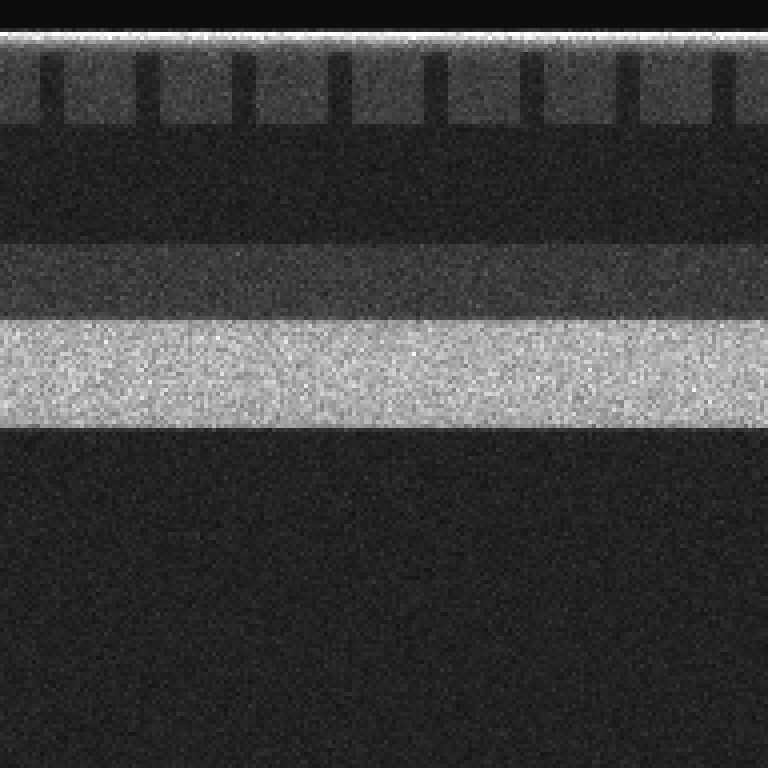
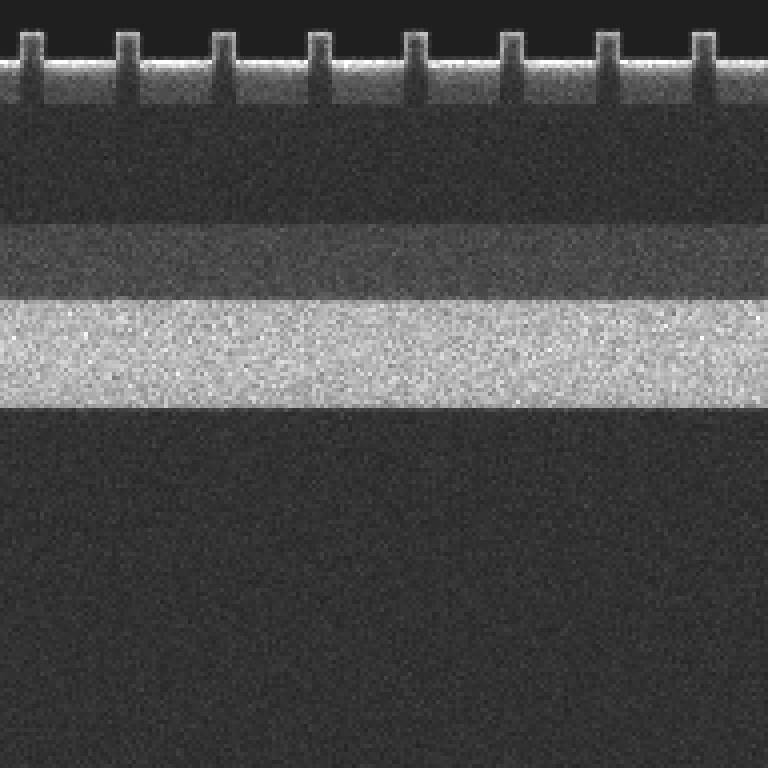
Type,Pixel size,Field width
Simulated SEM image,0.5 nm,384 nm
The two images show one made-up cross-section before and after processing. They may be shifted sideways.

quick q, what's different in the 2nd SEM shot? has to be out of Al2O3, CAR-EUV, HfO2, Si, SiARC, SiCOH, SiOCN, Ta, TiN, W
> SiARC removed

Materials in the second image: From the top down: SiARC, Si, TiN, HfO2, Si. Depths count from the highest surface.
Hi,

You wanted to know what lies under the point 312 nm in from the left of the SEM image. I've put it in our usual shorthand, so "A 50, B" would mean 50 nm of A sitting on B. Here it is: empty 14, SiARC 22, Si 60, TiN 38, HfO2 54, Si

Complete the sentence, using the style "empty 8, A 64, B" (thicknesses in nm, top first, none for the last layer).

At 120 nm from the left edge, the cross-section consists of empty 14, SiARC 22, Si 60, TiN 38, HfO2 54, Si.